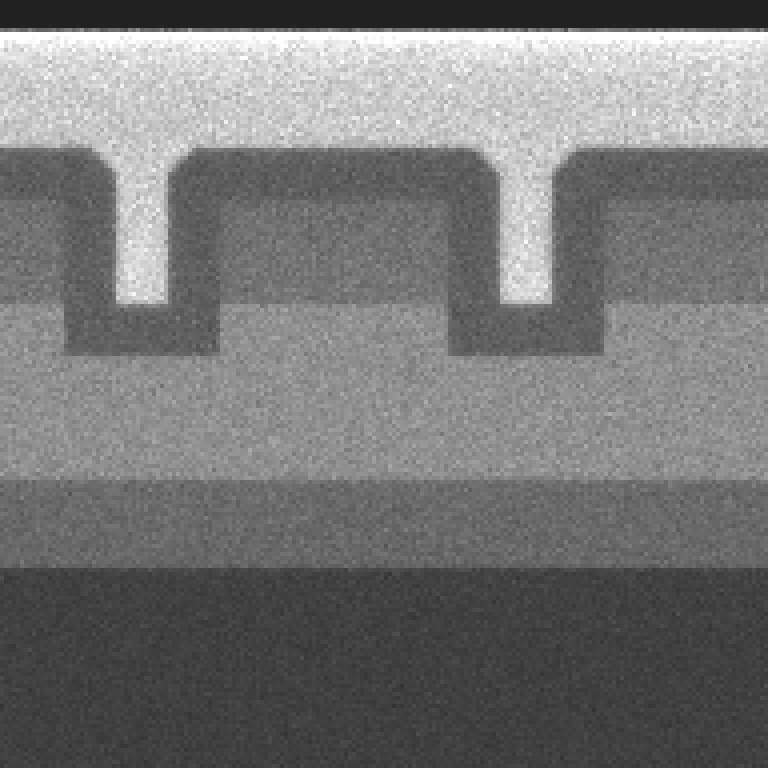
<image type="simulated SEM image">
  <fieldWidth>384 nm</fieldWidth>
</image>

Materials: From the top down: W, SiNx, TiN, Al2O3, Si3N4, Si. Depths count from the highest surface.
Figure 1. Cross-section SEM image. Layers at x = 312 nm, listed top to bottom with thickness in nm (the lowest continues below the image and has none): W 58, SiNx 26, TiN 52, Al2O3 88, Si3N4 44, Si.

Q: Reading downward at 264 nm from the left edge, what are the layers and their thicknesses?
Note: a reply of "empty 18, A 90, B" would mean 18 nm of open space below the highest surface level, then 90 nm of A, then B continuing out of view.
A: W 136, SiNx 26, Al2O3 62, Si3N4 44, Si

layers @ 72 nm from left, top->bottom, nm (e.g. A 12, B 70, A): W 136, SiNx 26, Al2O3 62, Si3N4 44, Si